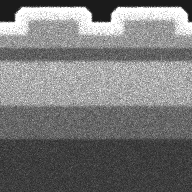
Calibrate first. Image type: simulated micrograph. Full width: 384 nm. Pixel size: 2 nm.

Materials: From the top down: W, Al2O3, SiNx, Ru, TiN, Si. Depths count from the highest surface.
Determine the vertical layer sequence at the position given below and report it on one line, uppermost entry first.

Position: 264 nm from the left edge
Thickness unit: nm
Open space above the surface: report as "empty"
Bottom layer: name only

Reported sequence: W 24, Al2O3 56, SiNx 26, Ru 90, TiN 66, Si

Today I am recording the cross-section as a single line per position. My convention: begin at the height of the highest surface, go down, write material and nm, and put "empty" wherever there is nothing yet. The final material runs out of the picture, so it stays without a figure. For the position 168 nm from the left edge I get W 54, Al2O3 26, SiNx 26, Ru 90, TiN 66, Si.